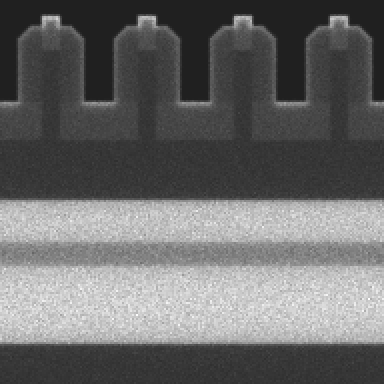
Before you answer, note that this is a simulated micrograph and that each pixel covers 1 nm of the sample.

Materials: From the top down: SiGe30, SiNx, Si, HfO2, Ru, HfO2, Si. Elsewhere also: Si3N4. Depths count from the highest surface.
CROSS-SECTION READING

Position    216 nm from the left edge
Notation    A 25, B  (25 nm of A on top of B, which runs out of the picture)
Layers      empty 16, SiGe30 70, SiNx 38, Si 60, HfO2 42, Ru 24, HfO2 78, Si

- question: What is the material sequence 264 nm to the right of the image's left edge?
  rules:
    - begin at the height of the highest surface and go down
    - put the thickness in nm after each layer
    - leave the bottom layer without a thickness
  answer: empty 12, SiGe30 74, SiNx 38, Si 60, HfO2 42, Ru 24, HfO2 78, Si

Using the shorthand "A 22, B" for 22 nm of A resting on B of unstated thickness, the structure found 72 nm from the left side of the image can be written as empty 12, SiGe30 74, SiNx 38, Si 60, HfO2 42, Ru 24, HfO2 78, Si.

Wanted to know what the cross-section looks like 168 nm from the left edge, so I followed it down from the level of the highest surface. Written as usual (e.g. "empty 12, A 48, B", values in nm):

empty 12, SiGe30 74, SiNx 38, Si 60, HfO2 42, Ru 24, HfO2 78, Si